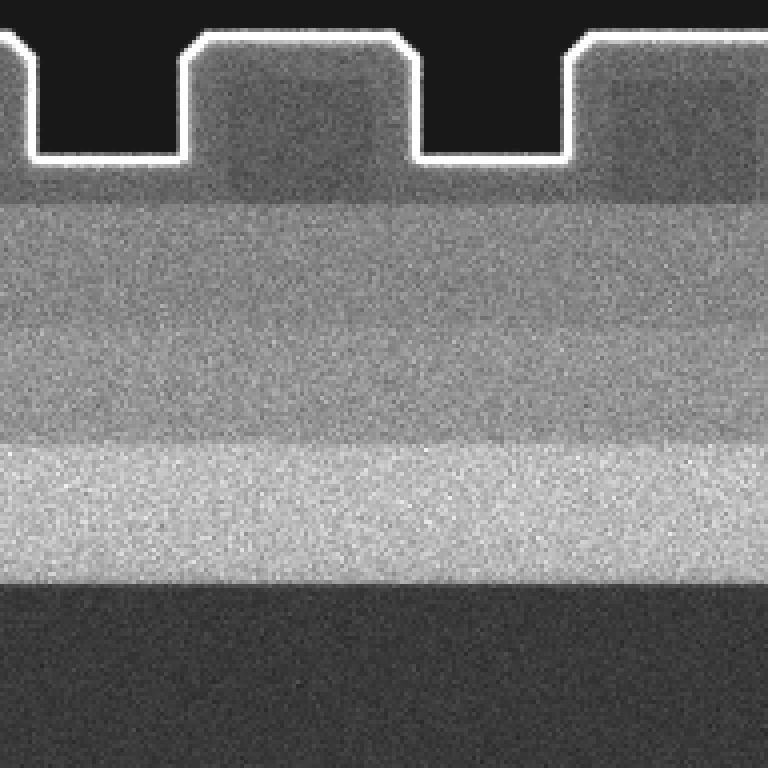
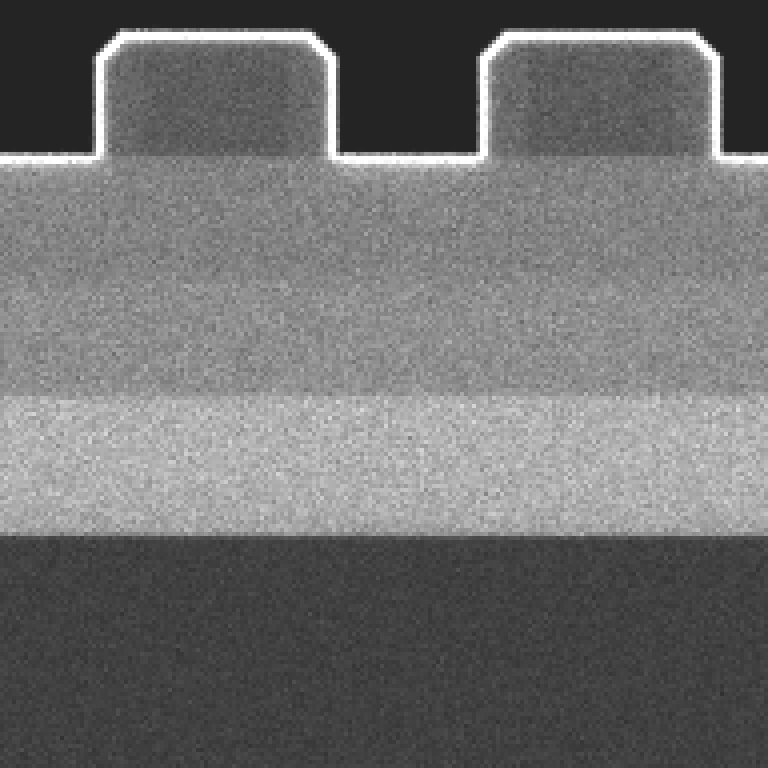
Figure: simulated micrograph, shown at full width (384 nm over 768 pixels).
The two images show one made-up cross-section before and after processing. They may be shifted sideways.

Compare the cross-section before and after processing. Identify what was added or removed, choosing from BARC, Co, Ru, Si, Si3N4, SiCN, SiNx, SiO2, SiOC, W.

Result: Si3N4 removed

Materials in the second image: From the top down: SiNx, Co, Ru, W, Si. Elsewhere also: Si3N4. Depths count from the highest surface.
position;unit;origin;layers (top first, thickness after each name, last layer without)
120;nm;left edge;SiNx 62, Co 62, Ru 58, W 70, Si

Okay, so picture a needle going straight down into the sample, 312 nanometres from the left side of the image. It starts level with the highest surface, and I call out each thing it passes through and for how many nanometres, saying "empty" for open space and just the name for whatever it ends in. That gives SiNx 62, Co 62, Ru 58, W 70, Si